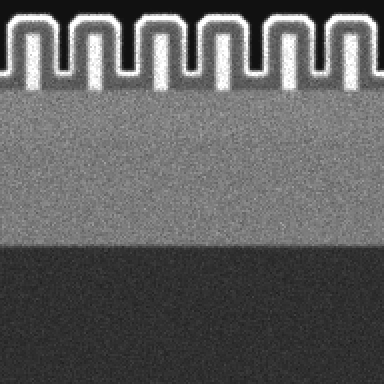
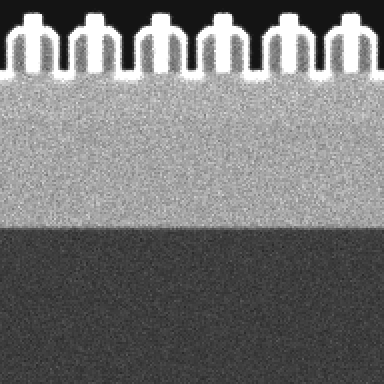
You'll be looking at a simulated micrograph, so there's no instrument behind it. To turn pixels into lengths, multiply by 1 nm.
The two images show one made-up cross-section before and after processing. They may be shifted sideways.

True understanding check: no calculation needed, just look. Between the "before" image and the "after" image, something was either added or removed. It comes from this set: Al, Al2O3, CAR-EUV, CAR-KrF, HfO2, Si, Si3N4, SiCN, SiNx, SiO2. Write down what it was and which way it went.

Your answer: Si3N4 (removed)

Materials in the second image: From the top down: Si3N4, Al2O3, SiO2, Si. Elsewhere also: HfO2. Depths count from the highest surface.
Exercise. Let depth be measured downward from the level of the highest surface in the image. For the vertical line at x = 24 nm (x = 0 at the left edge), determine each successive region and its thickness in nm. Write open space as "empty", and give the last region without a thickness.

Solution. empty 12, Si3N4 44, Al2O3 48, SiO2 108, Si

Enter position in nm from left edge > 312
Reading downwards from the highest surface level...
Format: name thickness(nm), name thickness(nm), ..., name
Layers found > empty 20, Si3N4 36, Al2O3 48, SiO2 108, Si